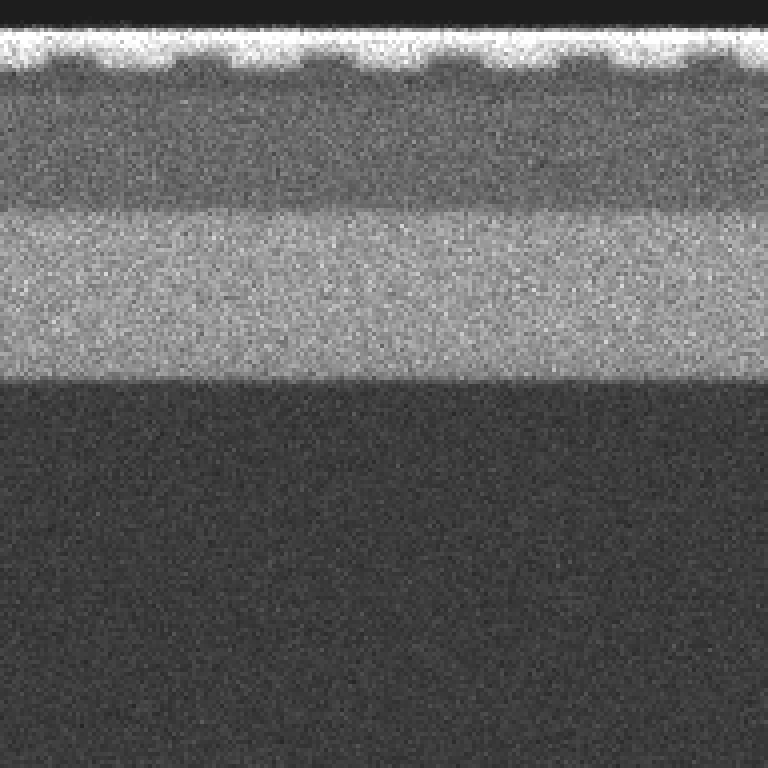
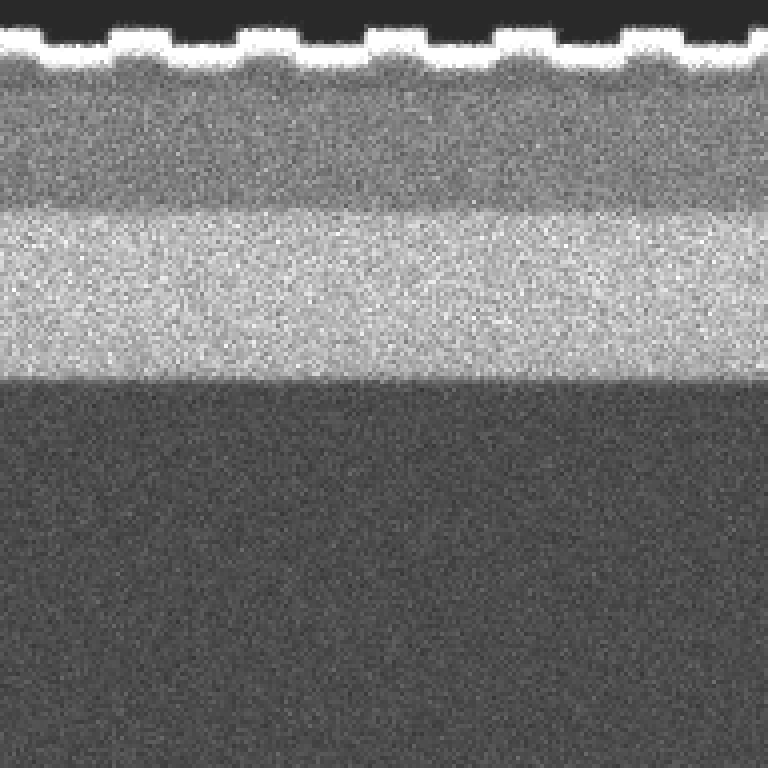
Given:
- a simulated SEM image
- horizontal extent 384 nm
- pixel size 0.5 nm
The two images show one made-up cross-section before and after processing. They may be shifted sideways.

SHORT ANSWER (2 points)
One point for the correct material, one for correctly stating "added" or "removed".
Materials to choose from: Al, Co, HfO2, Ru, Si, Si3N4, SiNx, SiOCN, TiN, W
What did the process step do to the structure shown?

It removed W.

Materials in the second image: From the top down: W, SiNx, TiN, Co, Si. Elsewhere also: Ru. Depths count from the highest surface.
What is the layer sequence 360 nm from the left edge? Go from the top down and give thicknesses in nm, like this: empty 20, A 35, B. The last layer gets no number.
empty 8, W 10, SiNx 12, TiN 60, Co 84, Si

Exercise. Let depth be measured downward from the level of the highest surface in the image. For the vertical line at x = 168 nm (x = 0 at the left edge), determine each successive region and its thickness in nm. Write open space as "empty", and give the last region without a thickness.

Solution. empty 8, W 10, SiNx 12, TiN 60, Co 84, Si